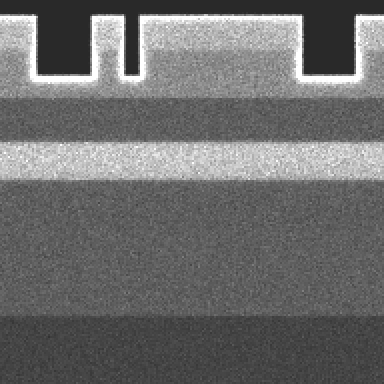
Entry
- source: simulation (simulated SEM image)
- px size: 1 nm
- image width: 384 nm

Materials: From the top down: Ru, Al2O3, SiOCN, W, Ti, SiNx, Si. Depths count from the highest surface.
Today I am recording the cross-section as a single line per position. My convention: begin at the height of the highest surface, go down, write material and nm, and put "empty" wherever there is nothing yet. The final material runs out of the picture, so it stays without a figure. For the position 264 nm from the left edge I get Ru 34, Al2O3 48, SiOCN 44, W 38, Ti 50, SiNx 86, Si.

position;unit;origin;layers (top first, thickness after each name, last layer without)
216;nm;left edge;Ru 34, Al2O3 48, SiOCN 44, W 38, Ti 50, SiNx 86, Si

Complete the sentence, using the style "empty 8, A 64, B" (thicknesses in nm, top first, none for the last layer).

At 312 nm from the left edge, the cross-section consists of empty 60, Al2O3 22, SiOCN 44, W 38, Ti 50, SiNx 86, Si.